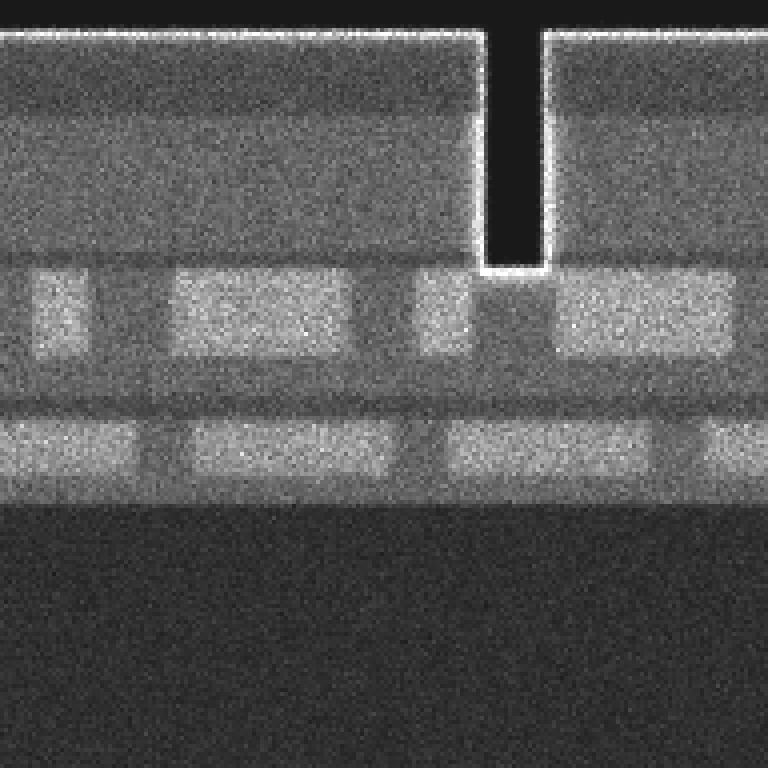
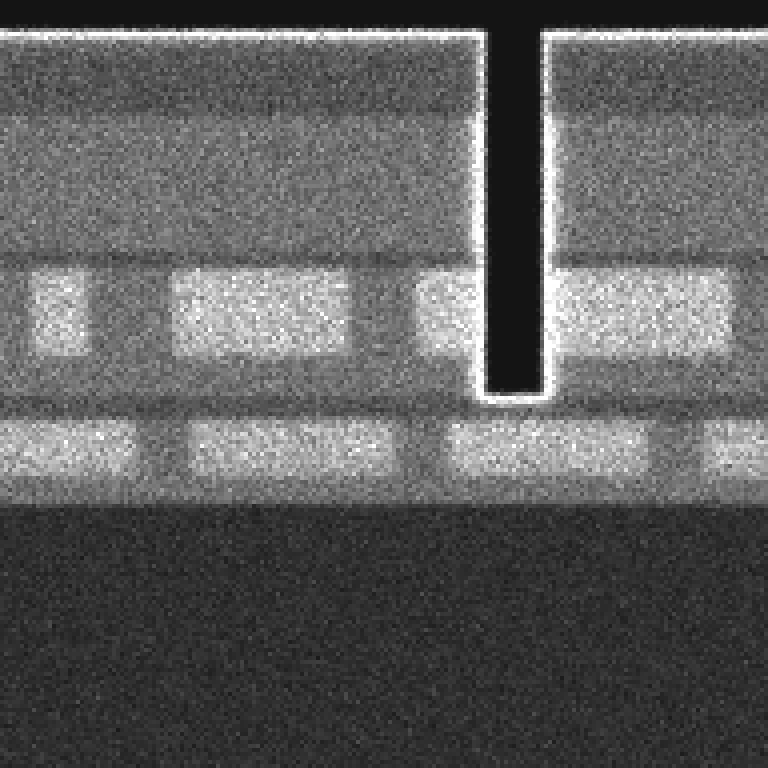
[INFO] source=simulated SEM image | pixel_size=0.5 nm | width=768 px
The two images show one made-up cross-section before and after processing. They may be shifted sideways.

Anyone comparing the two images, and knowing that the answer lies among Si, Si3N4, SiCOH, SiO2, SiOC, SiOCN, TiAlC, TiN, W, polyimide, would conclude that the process removed SiO2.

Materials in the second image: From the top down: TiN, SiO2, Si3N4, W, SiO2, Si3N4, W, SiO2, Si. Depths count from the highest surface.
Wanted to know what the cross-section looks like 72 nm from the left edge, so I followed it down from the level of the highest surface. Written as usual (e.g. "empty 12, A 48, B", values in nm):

TiN 42, SiO2 68, Si3N4 8, SiO2 64, Si3N4 12, SiO2 42, Si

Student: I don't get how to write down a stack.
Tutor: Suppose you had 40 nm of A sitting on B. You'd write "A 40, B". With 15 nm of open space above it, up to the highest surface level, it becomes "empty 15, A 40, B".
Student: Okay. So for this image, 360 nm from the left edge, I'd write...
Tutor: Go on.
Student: TiN 42, SiO2 68, Si3N4 8, W 44, SiO2 20, Si3N4 12, W 28, SiO2 14, Si